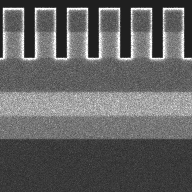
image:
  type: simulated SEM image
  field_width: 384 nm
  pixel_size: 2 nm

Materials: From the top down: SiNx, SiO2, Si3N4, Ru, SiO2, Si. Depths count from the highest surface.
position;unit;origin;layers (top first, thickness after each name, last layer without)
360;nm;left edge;SiNx 48, SiO2 52, Si3N4 68, Ru 48, SiO2 46, Si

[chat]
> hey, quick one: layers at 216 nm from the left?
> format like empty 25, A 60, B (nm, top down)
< SiNx 48, SiO2 52, Si3N4 68, Ru 48, SiO2 46, Si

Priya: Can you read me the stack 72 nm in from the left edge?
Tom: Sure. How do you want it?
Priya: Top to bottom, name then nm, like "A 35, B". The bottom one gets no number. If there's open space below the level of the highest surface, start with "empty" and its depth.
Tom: SiNx 48, SiO2 52, Si3N4 68, Ru 48, SiO2 46, Si